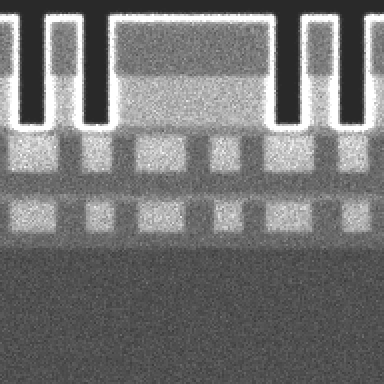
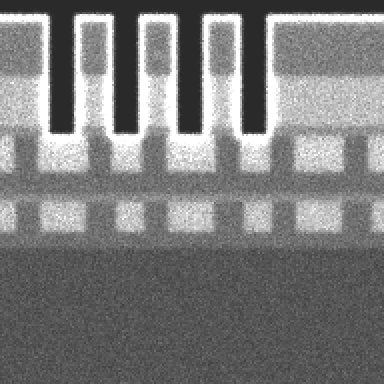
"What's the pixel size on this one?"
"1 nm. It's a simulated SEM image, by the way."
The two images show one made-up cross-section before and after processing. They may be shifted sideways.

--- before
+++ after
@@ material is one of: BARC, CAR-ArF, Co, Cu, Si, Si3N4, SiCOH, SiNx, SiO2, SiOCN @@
Si3N4 removed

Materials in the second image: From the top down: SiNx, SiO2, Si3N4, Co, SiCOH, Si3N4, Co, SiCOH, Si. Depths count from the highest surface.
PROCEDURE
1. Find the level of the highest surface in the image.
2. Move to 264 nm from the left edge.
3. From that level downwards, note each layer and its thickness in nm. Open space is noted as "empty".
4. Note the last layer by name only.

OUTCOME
empty 120, Co 36, SiCOH 22, Si3N4 8, Co 30, SiCOH 16, Si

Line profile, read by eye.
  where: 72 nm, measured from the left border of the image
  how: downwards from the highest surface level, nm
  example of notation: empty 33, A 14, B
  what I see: empty 120, Co 36, SiCOH 22, Si3N4 8, Co 30, SiCOH 16, Si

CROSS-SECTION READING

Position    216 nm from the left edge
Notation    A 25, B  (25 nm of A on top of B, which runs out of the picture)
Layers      SiNx 60, SiO2 50, Si3N4 10, SiCOH 58, Si3N4 8, SiCOH 46, Si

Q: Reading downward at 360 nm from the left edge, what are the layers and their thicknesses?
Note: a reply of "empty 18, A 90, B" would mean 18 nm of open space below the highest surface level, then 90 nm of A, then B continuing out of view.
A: SiNx 60, SiO2 50, Si3N4 10, SiCOH 58, Si3N4 8, SiCOH 46, Si